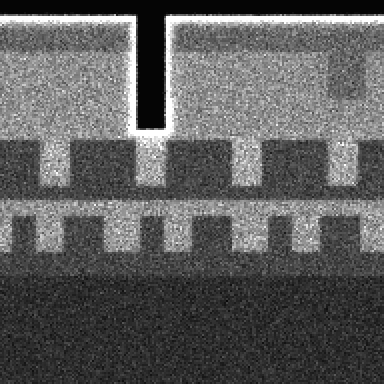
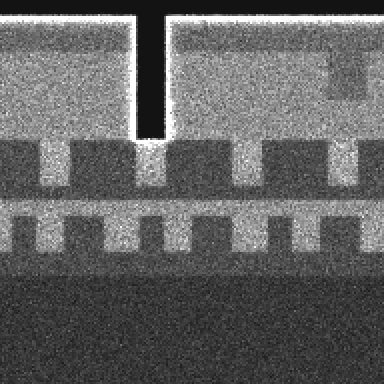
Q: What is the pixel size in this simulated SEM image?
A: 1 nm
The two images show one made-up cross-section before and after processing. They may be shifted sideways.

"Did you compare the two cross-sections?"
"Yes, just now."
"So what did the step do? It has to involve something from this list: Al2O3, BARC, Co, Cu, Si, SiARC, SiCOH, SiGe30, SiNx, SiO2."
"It removed Al2O3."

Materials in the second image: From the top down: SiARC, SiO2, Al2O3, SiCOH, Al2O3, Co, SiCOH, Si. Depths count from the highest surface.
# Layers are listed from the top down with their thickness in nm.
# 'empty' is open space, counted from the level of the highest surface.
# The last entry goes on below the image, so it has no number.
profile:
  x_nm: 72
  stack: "SiARC 36, SiO2 78, Al2O3 10, SiCOH 60, Al2O3 16, SiCOH 60, Si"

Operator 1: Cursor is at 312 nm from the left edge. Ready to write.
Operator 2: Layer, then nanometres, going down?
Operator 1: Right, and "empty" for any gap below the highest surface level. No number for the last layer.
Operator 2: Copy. SiARC 36, SiO2 78, Al2O3 10, SiCOH 60, Al2O3 16, Co 36, SiCOH 24, Si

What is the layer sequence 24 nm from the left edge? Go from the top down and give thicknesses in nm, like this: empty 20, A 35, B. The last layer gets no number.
SiARC 36, SiO2 78, Al2O3 10, SiCOH 60, Al2O3 16, SiCOH 60, Si